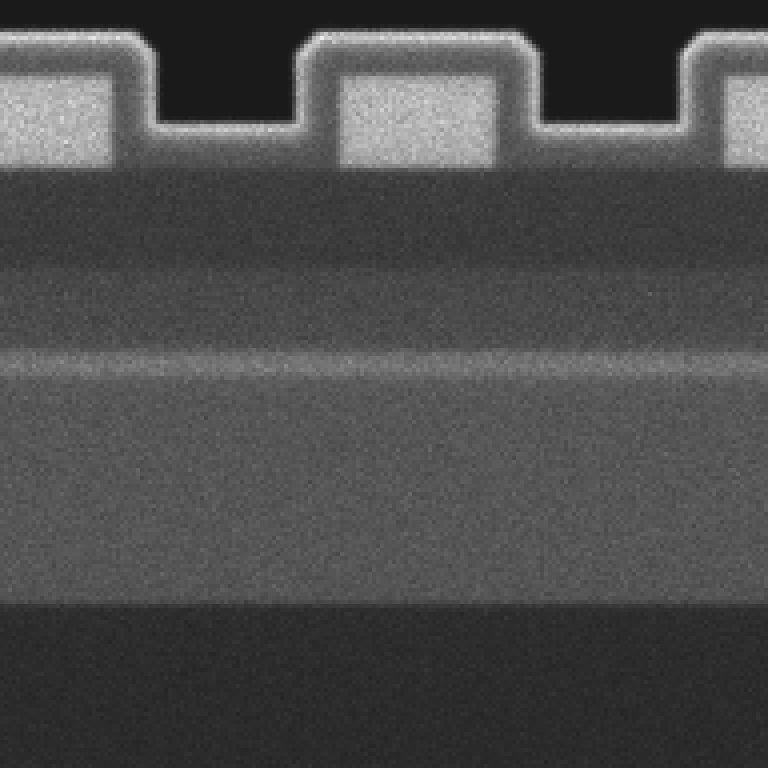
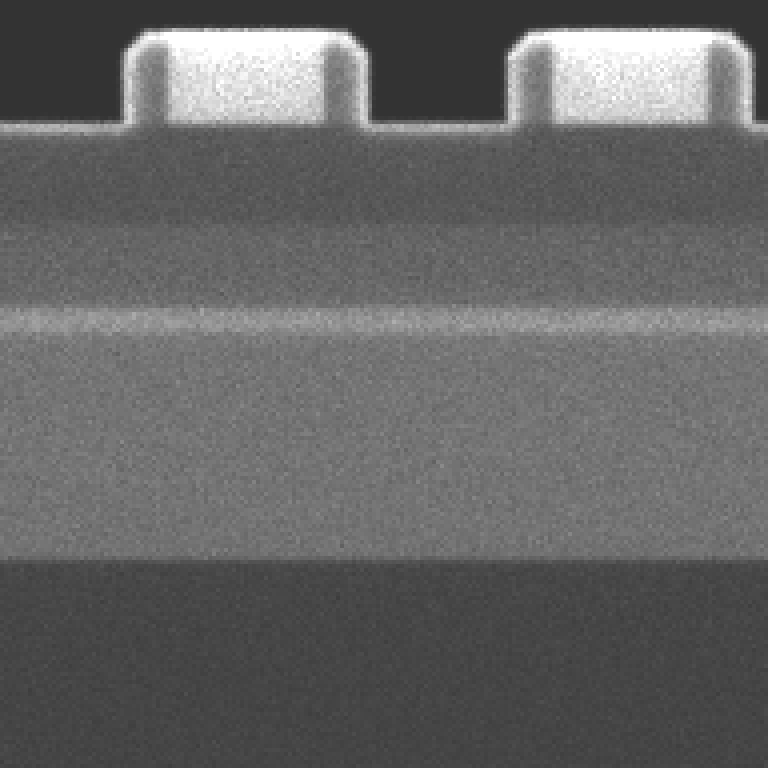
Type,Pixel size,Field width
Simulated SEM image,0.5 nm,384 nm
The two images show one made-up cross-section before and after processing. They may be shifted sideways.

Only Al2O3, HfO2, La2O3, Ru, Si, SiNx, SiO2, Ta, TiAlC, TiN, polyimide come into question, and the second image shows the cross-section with SiO2 removed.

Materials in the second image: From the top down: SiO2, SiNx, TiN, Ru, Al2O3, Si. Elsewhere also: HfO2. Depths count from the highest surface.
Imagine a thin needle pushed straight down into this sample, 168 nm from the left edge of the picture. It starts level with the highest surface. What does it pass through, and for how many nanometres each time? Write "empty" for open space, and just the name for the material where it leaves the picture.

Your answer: SiO2 46, SiNx 50, TiN 42, Ru 12, Al2O3 114, Si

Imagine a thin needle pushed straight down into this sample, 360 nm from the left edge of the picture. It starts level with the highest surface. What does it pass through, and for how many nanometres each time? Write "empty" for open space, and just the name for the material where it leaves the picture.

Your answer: SiO2 46, SiNx 50, TiN 42, Ru 12, Al2O3 114, Si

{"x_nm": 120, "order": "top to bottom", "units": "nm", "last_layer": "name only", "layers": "HfO2 46, SiNx 50, TiN 42, Ru 12, Al2O3 114, Si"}